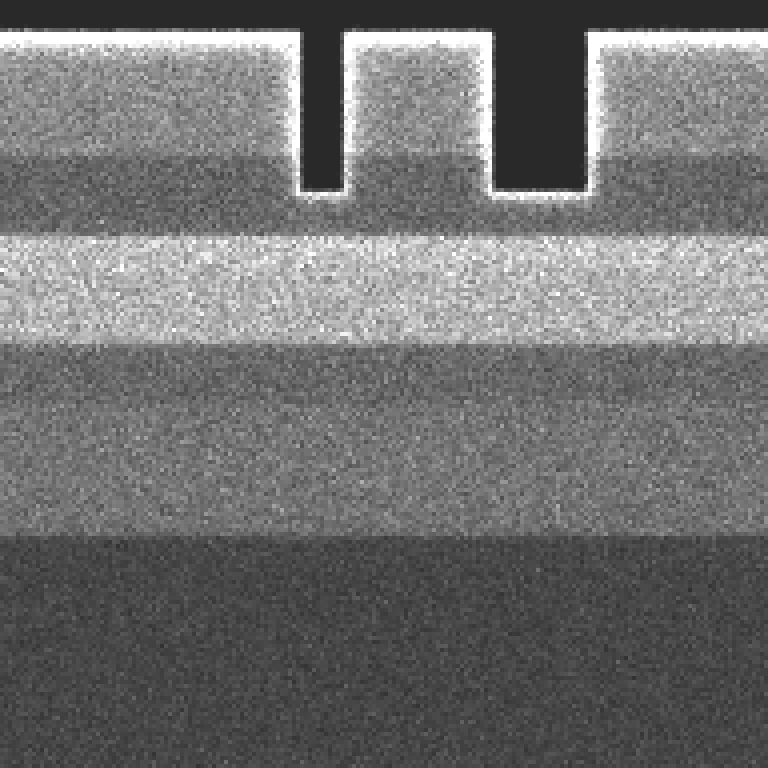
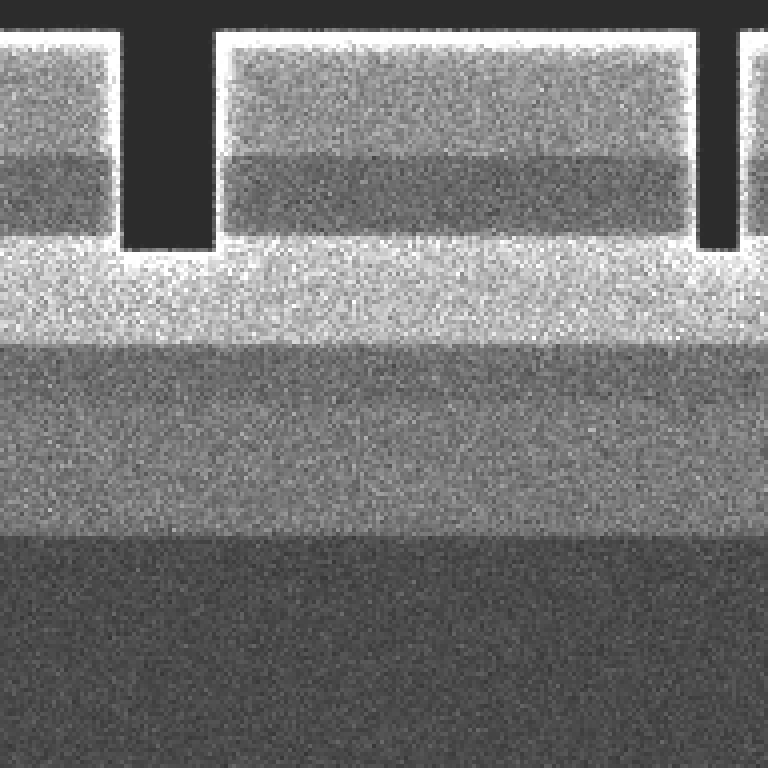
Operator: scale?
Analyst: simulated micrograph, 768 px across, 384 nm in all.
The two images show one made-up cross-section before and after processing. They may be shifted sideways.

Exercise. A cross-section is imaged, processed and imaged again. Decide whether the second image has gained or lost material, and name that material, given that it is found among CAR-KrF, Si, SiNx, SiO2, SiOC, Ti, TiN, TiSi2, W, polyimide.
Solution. removed: SiNx and W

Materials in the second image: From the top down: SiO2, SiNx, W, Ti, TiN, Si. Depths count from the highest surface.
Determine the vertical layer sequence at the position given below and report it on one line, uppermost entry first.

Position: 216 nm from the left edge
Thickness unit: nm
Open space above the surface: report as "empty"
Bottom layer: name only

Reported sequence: SiO2 62, SiNx 40, W 54, Ti 30, TiN 66, Si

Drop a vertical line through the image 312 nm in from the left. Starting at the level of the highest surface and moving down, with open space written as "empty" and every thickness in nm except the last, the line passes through SiO2 62, SiNx 40, W 54, Ti 30, TiN 66, Si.